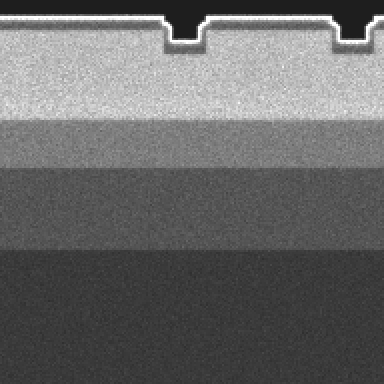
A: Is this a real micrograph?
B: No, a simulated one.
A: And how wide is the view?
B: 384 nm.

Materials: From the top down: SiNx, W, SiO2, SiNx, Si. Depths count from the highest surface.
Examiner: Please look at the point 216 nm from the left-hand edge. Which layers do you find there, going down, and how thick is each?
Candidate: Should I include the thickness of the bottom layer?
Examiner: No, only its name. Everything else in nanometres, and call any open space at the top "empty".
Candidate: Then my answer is SiNx 14, W 90, SiO2 48, SiNx 82, Si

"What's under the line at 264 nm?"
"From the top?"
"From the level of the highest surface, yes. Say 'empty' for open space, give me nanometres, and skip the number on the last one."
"SiNx 14, W 90, SiO2 48, SiNx 82, Si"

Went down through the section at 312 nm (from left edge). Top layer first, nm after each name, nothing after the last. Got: SiNx 14, W 90, SiO2 48, SiNx 82, Si